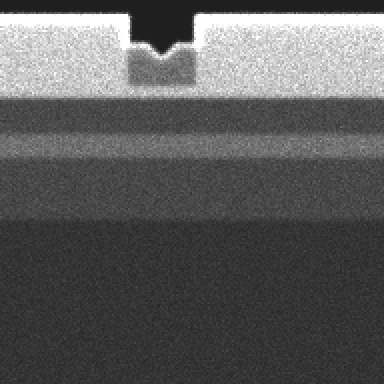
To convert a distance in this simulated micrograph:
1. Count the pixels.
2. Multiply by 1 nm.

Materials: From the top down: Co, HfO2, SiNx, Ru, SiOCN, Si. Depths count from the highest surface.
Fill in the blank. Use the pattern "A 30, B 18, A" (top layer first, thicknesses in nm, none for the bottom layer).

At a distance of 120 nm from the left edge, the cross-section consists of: HfO2 82, SiNx 36, Ru 24, SiOCN 62, Si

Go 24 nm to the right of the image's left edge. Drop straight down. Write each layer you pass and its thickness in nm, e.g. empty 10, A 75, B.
HfO2 82, SiNx 36, Ru 24, SiOCN 62, Si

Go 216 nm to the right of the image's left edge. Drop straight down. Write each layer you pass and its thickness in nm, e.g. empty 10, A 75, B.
HfO2 82, SiNx 36, Ru 24, SiOCN 62, Si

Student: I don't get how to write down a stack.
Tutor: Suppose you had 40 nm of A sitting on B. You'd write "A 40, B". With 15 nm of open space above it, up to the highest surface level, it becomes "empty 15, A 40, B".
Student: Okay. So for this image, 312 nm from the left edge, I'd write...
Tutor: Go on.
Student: HfO2 82, SiNx 36, Ru 24, SiOCN 62, Si